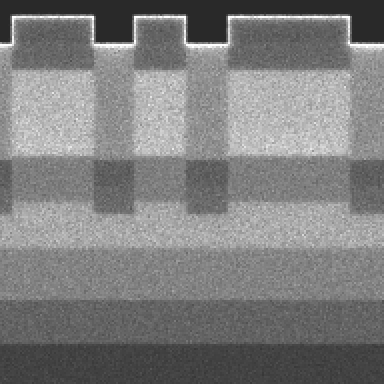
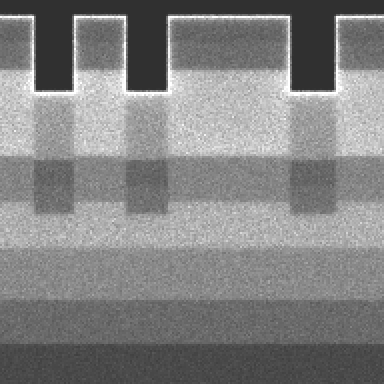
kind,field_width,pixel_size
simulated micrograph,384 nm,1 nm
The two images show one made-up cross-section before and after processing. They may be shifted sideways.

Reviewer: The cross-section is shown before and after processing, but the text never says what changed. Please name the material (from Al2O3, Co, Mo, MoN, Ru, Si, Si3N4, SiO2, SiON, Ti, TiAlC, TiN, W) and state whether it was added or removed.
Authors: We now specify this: Co, removed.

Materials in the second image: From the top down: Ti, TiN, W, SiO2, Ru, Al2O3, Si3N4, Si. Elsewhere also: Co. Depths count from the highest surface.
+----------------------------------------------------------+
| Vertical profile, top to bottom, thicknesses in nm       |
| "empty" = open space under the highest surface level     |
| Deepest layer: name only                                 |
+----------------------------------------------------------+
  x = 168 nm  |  Ti 26, TiN 28, W 86, SiO2 46, Ru 46, Al2O3 52, Si3N4 44, Si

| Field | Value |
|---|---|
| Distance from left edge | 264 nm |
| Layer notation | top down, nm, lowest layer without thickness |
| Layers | Ti 26, TiN 28, W 86, SiO2 46, Ru 46, Al2O3 52, Si3N4 44, Si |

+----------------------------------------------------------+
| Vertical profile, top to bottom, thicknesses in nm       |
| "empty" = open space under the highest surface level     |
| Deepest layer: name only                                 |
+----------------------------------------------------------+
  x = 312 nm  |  empty 76, Co 68, Ti 26, TiN 28, Ru 34, Al2O3 52, Si3N4 44, Si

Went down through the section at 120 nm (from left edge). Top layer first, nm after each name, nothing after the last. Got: Ti 26, TiN 28, W 86, SiO2 46, Ru 46, Al2O3 52, Si3N4 44, Si